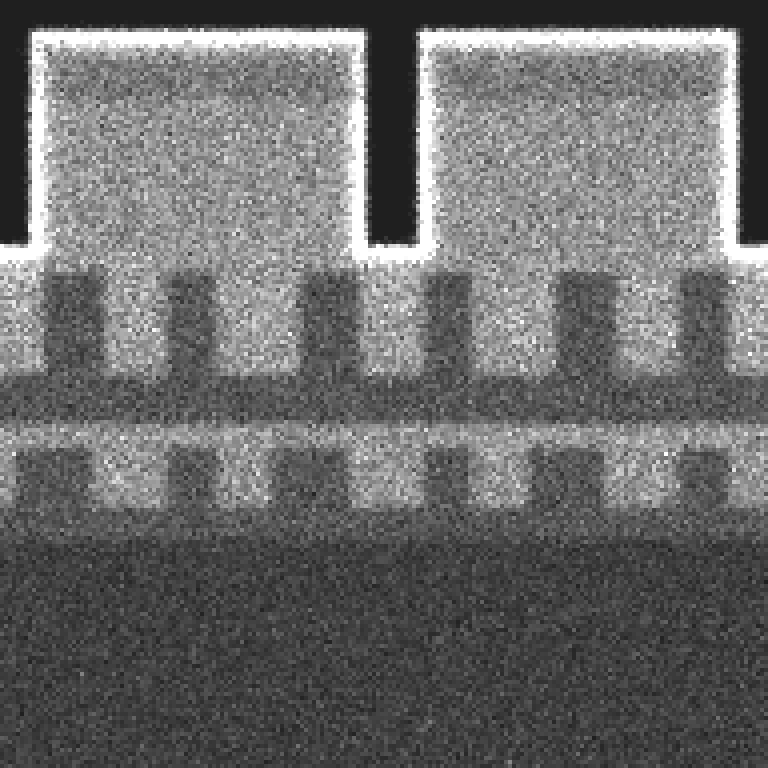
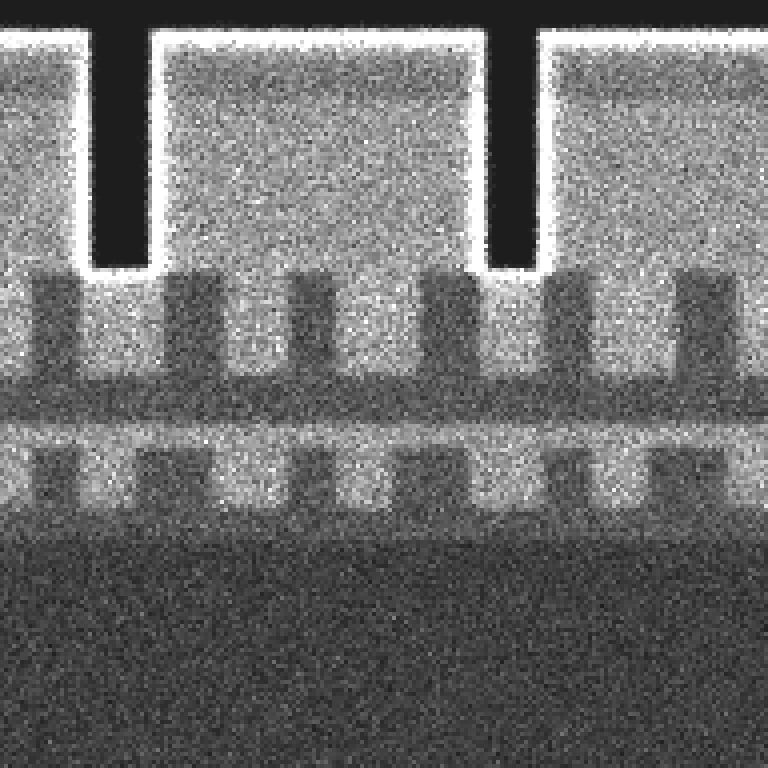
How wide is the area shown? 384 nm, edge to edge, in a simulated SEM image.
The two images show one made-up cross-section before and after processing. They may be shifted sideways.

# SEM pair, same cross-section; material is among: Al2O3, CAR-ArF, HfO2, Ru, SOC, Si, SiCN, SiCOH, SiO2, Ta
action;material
removed;Al2O3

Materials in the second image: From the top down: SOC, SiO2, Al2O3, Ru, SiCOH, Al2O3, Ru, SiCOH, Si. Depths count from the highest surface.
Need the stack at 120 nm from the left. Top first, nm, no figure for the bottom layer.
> SOC 34, SiO2 74, Al2O3 12, Ru 52, SiCOH 24, Al2O3 12, Ru 30, SiCOH 16, Si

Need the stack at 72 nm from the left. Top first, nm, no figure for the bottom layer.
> empty 120, Ru 52, SiCOH 24, Al2O3 12, SiCOH 46, Si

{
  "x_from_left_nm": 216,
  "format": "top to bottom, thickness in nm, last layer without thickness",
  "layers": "SOC 34, SiO2 74, Al2O3 12, SiCOH 76, Al2O3 12, SiCOH 46, Si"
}